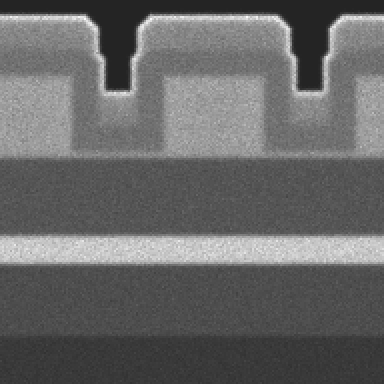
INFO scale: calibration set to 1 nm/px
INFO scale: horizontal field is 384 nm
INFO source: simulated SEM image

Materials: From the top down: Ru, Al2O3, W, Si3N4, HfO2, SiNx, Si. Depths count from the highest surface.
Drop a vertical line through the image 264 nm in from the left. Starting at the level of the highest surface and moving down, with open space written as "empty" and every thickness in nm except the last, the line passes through Ru 34, Al2O3 102, W 6, Si3N4 78, HfO2 28, SiNx 72, Si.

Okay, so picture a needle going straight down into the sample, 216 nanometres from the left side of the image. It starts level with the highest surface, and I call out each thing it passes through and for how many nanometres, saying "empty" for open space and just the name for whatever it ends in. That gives Ru 34, Al2O3 26, W 82, Si3N4 78, HfO2 28, SiNx 72, Si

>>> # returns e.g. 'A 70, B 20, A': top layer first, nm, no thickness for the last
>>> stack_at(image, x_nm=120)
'empty 76, Ru 34, Al2O3 26, W 6, Si3N4 78, HfO2 28, SiNx 72, Si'